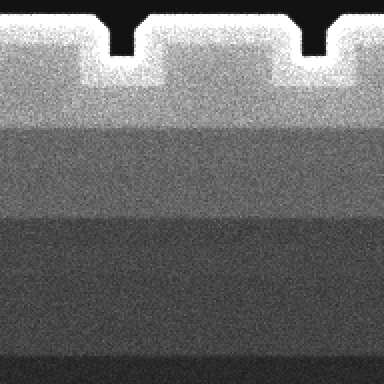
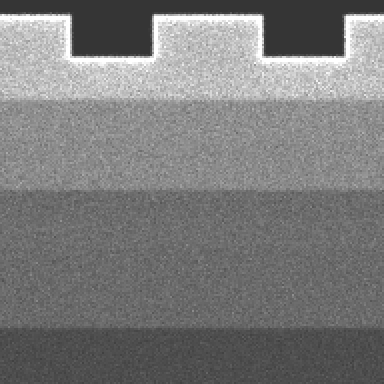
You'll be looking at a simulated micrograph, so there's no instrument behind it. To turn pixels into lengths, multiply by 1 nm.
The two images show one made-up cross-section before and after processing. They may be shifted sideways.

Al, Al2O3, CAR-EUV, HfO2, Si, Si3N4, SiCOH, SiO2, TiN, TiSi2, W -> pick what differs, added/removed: HfO2 removed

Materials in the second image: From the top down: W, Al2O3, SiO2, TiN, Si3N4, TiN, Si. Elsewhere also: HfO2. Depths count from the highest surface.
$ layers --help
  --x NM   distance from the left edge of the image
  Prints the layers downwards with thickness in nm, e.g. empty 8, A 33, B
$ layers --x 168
W 84, Al2O3 40, SiO2 50, TiN 28, Si3N4 30, TiN 80, Si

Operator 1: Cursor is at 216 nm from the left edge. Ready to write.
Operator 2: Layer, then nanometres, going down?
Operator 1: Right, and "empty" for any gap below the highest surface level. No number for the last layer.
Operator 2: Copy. W 84, Al2O3 40, SiO2 50, TiN 28, Si3N4 30, TiN 80, Si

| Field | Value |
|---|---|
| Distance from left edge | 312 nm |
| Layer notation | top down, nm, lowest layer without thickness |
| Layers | empty 42, W 42, Al2O3 40, SiO2 50, TiN 28, Si3N4 30, TiN 80, Si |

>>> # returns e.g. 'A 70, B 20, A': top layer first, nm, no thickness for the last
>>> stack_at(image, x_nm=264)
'empty 42, W 42, Al2O3 40, SiO2 50, TiN 28, Si3N4 30, TiN 80, Si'